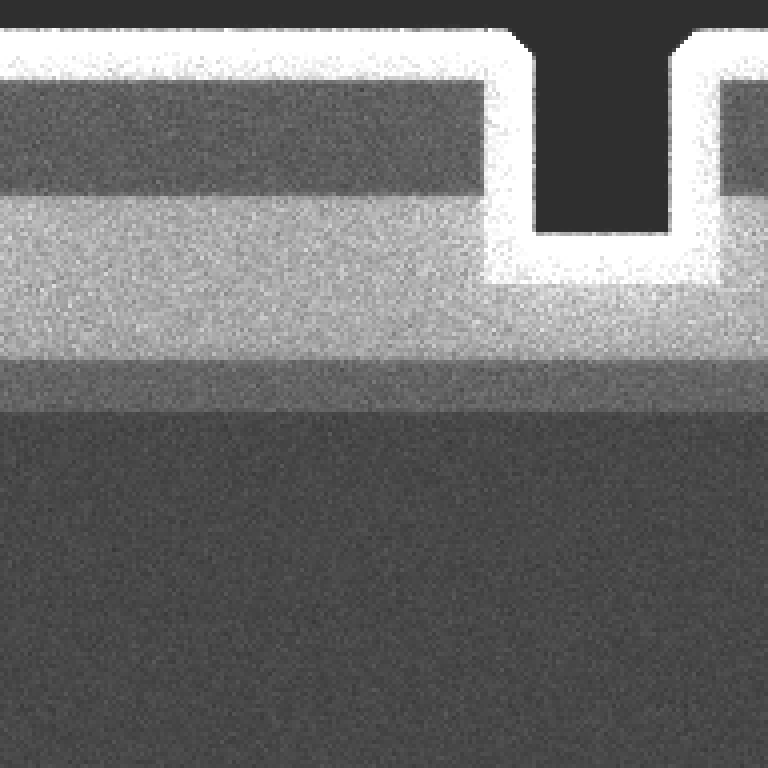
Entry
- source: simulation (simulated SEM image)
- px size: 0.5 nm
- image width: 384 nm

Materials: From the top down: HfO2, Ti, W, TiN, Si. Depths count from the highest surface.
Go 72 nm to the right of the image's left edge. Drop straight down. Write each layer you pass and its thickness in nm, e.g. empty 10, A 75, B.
HfO2 24, Ti 58, W 82, TiN 26, Si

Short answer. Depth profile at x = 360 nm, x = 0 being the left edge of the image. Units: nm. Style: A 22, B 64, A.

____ HfO2 24, Ti 58, W 82, TiN 26, Si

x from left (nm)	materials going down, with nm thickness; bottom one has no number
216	HfO2 24, Ti 58, W 82, TiN 26, Si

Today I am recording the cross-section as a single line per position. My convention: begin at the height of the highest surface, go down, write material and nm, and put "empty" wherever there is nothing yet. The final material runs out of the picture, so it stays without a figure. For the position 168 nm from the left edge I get HfO2 24, Ti 58, W 82, TiN 26, Si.